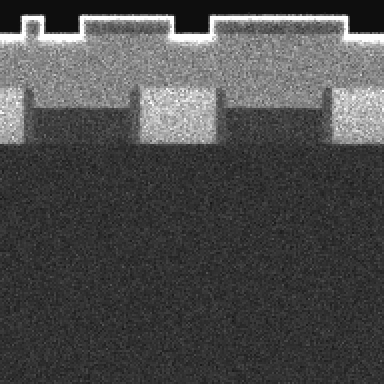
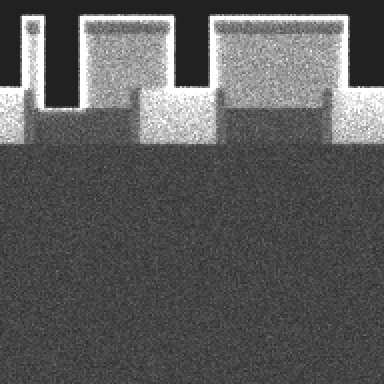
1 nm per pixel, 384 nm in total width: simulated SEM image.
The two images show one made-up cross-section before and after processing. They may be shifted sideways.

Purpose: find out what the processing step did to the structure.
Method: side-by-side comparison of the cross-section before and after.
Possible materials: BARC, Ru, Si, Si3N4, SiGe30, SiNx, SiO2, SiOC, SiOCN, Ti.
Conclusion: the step removed SiO2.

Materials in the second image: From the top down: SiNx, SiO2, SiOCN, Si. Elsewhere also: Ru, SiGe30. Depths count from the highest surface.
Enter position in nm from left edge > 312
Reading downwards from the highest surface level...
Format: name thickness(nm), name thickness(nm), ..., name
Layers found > SiNx 18, SiO2 74, SiGe30 36, Si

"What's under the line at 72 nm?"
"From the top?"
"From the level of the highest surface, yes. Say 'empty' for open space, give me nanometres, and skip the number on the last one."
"empty 92, SiGe30 36, Si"